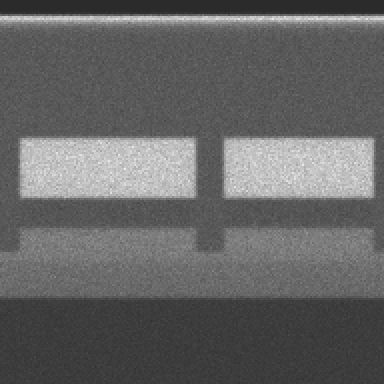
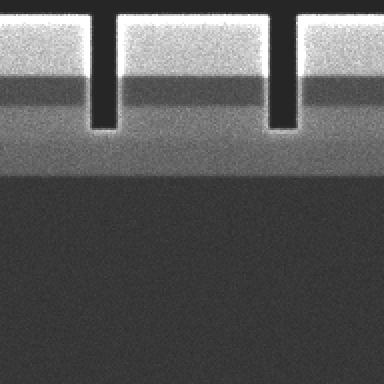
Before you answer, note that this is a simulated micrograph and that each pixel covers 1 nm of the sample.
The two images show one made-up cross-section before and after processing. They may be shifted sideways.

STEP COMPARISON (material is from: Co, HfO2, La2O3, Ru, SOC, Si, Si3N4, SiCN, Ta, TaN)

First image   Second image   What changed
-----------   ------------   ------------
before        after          SOC, removed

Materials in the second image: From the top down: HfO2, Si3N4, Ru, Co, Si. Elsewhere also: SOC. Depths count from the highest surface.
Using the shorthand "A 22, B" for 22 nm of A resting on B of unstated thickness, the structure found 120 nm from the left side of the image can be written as HfO2 60, Si3N4 30, Ru 34, Co 36, Si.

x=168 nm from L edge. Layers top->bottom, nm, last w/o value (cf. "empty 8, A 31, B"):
HfO2 60, Si3N4 30, Ru 34, Co 36, Si